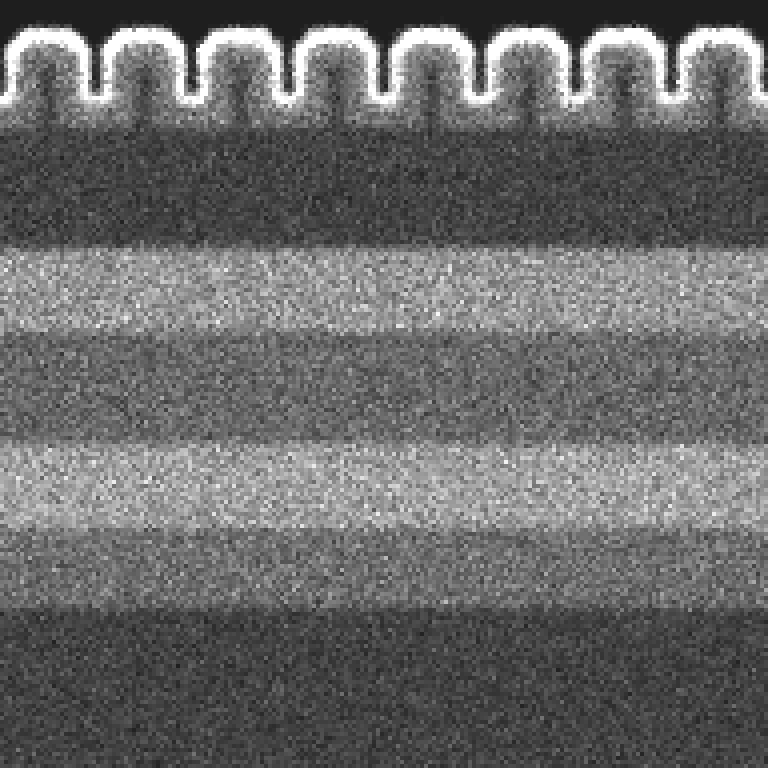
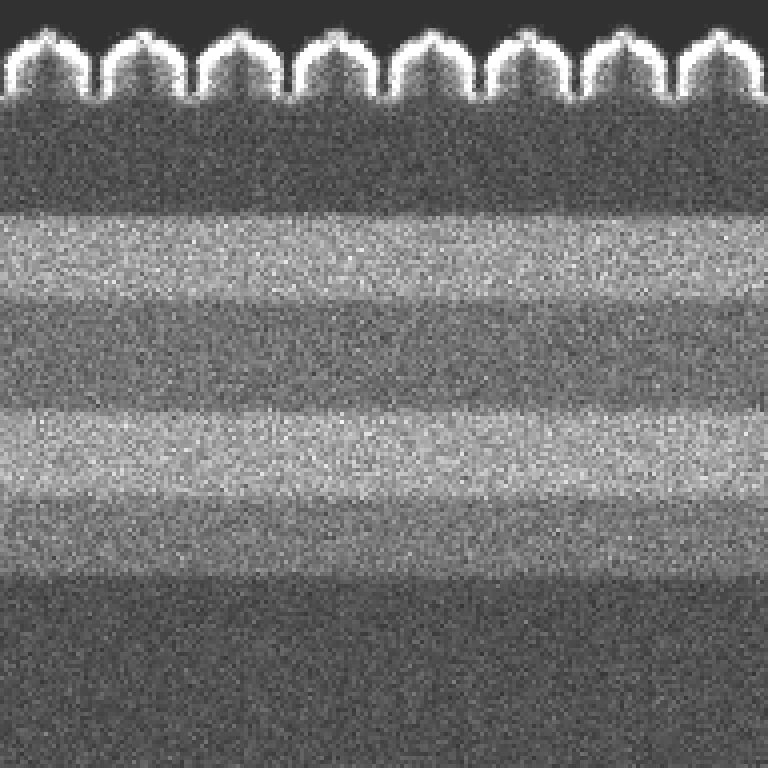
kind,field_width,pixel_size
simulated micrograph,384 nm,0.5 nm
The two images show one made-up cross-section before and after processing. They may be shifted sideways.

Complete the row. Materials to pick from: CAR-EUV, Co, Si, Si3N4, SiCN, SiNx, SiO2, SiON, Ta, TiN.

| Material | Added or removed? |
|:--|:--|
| Si3N4 | removed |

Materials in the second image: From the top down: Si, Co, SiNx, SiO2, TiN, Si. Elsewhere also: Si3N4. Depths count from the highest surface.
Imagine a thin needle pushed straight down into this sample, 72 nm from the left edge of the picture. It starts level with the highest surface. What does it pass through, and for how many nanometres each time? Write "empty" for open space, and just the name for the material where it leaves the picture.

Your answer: Si 92, Co 42, SiNx 56, SiO2 42, TiN 40, Si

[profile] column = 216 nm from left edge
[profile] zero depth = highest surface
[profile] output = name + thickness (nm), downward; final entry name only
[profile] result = Si 92, Co 42, SiNx 56, SiO2 42, TiN 40, Si